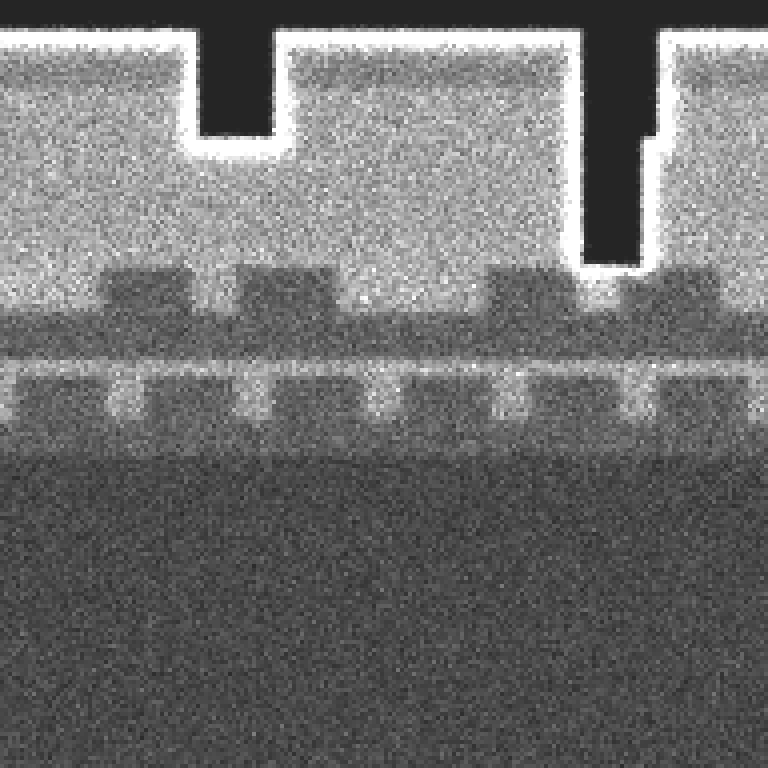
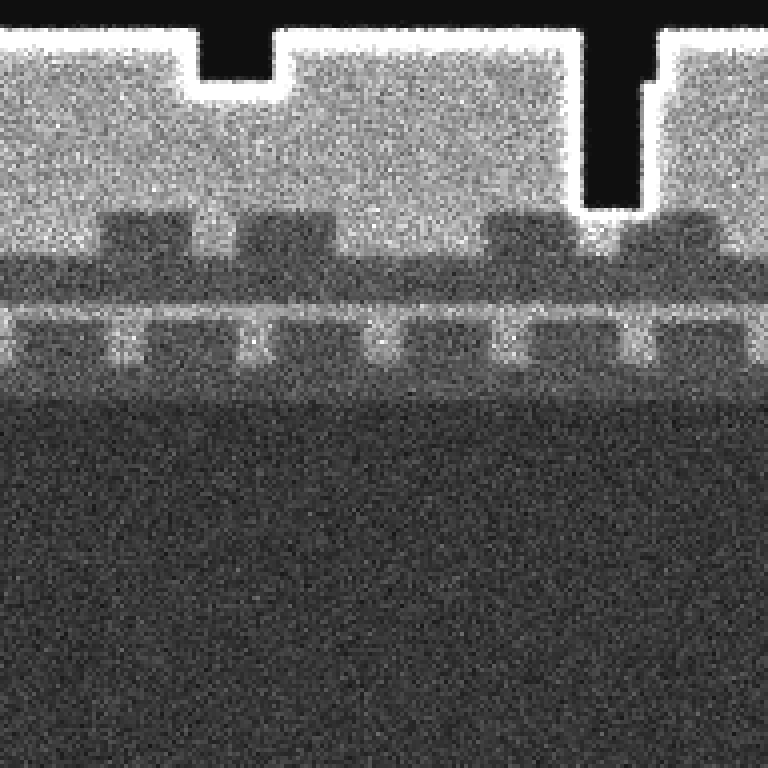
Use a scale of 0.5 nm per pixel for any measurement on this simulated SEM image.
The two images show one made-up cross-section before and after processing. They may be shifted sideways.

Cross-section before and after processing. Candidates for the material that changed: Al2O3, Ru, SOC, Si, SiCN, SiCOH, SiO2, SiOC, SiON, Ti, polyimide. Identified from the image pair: SOC (removed).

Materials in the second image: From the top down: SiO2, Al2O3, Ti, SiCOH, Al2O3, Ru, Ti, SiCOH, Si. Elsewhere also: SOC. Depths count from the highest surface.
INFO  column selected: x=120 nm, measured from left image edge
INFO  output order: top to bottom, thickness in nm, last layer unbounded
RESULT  empty 26, SiO2 48, Al2O3 16, Ti 28, SiCOH 18, Al2O3 8, Ru 22, Ti 6, SiCOH 12, Si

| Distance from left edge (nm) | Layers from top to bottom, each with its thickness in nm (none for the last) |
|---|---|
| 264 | SiO2 74, Al2O3 16, SiCOH 46, Al2O3 8, Ti 28, SiCOH 12, Si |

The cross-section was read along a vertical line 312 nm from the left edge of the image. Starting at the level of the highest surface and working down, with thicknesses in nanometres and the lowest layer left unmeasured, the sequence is empty 90, Ti 28, SiCOH 18, Al2O3 8, Ru 22, Ti 6, SiCOH 12, Si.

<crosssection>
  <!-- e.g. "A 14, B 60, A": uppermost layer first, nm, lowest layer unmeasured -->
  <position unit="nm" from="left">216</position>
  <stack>SiO2 74, Al2O3 16, Ru 22, Ti 6, SiCOH 18, Al2O3 8, SiCOH 40, Si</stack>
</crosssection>